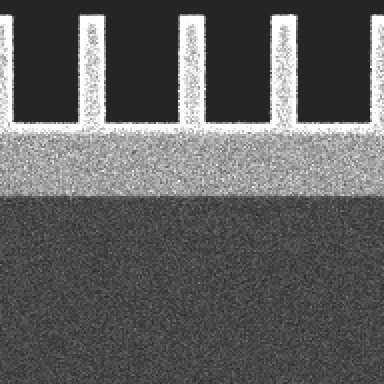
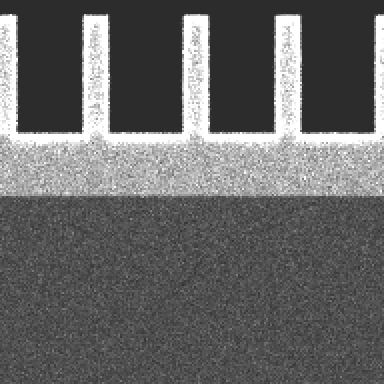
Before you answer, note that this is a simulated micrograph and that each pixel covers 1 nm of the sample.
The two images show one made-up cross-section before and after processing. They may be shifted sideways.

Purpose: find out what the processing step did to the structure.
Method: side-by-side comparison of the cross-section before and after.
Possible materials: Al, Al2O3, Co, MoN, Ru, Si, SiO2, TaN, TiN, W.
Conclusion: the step removed Ru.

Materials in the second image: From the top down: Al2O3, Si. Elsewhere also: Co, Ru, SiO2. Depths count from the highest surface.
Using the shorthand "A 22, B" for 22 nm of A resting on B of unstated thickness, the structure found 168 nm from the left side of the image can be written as empty 118, Al2O3 62, Si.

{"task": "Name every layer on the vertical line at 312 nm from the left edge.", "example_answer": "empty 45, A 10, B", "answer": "empty 118, Al2O3 62, Si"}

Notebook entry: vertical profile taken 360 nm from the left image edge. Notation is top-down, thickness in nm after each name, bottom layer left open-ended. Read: empty 118, Al2O3 62, Si